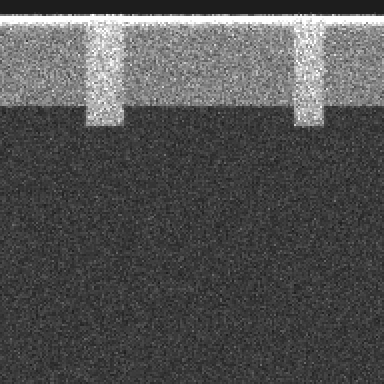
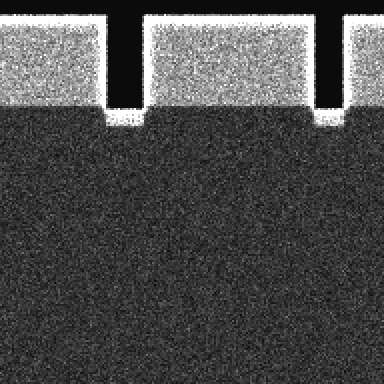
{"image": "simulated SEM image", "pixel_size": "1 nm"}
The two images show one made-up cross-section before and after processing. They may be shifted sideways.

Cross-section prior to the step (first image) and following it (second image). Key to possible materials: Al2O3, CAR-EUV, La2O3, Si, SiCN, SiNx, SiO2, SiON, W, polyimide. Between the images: W was removed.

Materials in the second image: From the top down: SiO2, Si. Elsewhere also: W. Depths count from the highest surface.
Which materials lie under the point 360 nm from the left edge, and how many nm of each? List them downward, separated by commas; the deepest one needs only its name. SiO2 90, Si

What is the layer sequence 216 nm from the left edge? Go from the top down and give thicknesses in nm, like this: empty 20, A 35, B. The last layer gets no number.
SiO2 90, Si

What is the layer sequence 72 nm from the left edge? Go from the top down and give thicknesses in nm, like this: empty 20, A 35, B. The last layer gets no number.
SiO2 90, Si